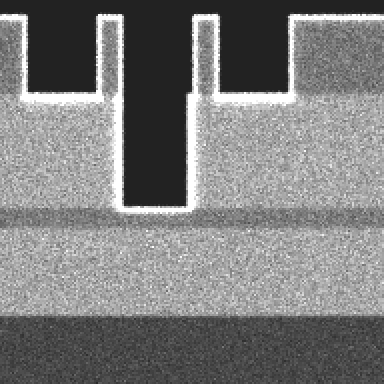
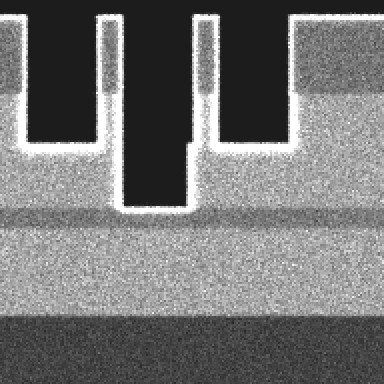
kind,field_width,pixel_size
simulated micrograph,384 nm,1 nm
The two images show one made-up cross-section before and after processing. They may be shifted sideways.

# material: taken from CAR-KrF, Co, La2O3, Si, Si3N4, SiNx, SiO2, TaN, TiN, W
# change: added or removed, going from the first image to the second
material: SiO2
change: removed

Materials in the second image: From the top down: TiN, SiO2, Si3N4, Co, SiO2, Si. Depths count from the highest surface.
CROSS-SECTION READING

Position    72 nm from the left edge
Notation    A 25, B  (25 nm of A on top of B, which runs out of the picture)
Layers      empty 128, SiO2 64, Si3N4 20, Co 50, SiO2 38, Si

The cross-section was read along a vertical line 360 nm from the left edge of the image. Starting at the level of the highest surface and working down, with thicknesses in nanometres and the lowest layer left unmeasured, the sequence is TiN 78, SiO2 114, Si3N4 20, Co 50, SiO2 38, Si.